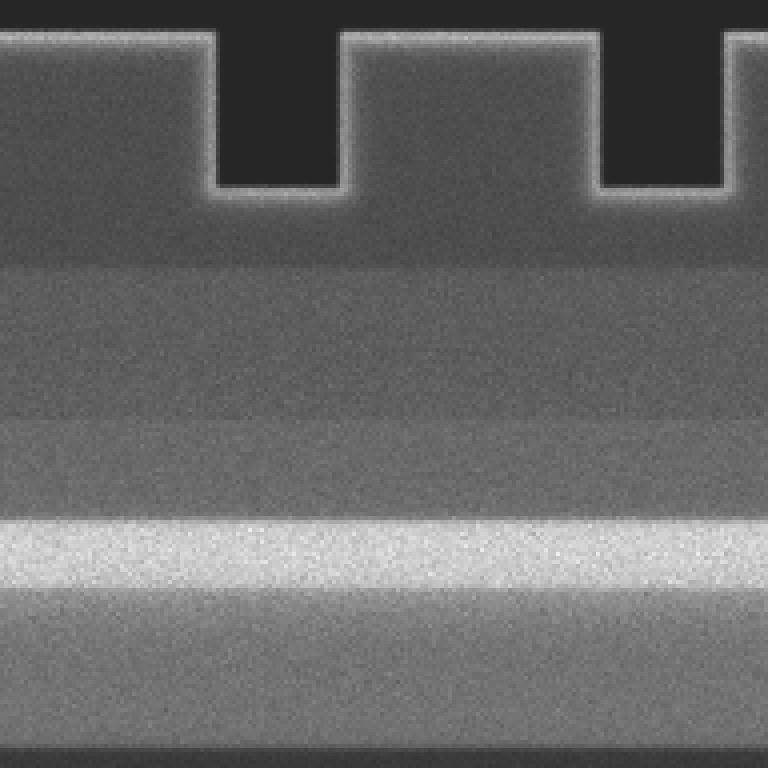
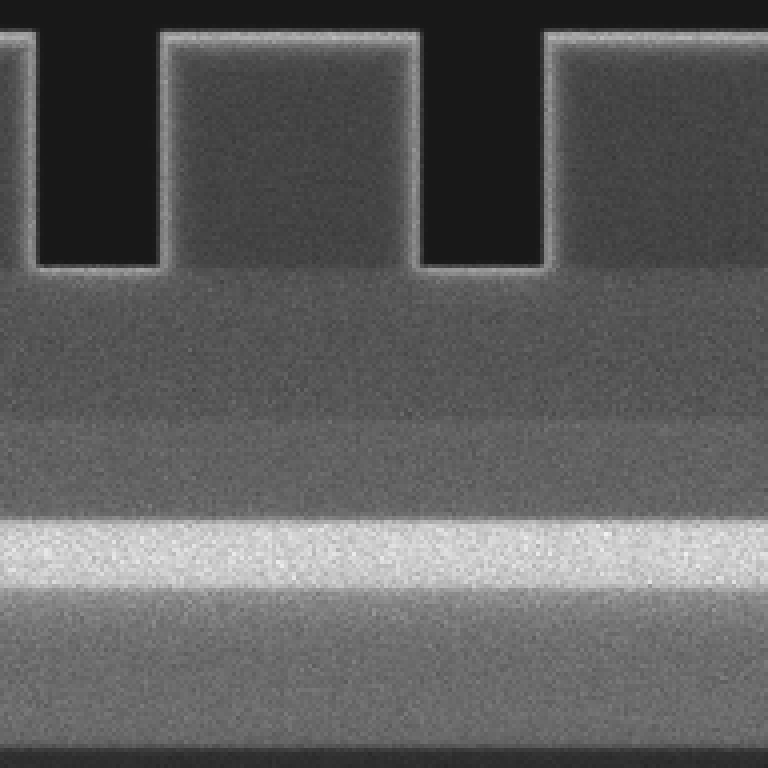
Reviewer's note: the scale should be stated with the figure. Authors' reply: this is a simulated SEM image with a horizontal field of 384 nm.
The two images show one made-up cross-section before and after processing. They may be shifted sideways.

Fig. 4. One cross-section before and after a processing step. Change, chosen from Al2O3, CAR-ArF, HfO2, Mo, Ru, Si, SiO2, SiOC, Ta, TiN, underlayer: underlayer removed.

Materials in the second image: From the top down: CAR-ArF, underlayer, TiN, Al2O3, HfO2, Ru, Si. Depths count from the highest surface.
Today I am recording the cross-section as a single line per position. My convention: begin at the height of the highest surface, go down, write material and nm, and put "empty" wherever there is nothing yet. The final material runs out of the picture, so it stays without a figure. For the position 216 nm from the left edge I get empty 118, TiN 76, Al2O3 50, HfO2 34, Ru 80, Si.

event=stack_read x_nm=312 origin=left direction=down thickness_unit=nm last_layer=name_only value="CAR-ArF 78, underlayer 40, TiN 76, Al2O3 50, HfO2 34, Ru 80, Si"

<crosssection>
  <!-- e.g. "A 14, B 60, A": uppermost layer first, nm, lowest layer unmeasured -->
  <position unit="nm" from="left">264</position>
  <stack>empty 118, TiN 76, Al2O3 50, HfO2 34, Ru 80, Si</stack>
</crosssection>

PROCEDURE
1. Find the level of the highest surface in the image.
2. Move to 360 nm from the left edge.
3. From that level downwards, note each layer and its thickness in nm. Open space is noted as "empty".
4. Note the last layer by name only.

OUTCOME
CAR-ArF 78, underlayer 40, TiN 76, Al2O3 50, HfO2 34, Ru 80, Si